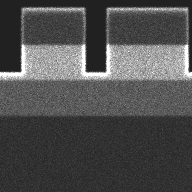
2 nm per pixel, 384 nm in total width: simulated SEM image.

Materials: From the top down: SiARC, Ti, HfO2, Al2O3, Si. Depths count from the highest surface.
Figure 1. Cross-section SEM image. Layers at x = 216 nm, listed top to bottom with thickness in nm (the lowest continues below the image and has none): SiARC 12, Ti 62, HfO2 70, Al2O3 72, Si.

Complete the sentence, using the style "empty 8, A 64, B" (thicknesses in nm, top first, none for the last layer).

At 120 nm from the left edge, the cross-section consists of SiARC 12, Ti 62, HfO2 70, Al2O3 72, Si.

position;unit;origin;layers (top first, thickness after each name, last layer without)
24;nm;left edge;empty 130, HfO2 14, Al2O3 72, Si